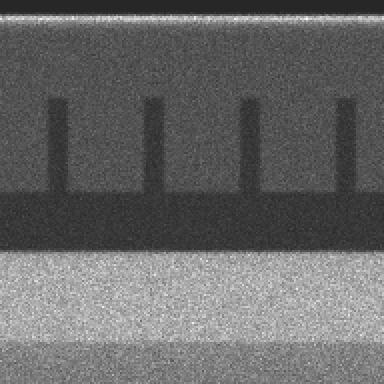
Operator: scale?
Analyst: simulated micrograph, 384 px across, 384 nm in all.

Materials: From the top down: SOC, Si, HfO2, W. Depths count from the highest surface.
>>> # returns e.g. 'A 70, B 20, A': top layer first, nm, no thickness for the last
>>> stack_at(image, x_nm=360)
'SOC 176, Si 60, HfO2 90, W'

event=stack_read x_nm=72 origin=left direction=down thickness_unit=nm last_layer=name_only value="SOC 176, Si 60, HfO2 90, W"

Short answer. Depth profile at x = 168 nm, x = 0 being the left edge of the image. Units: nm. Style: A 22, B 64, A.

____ SOC 176, Si 60, HfO2 90, W